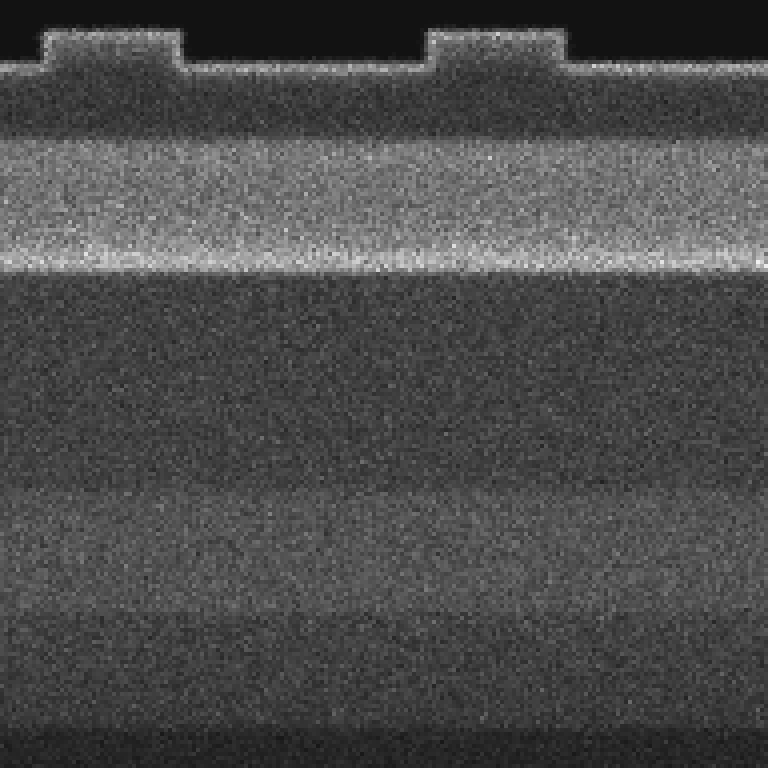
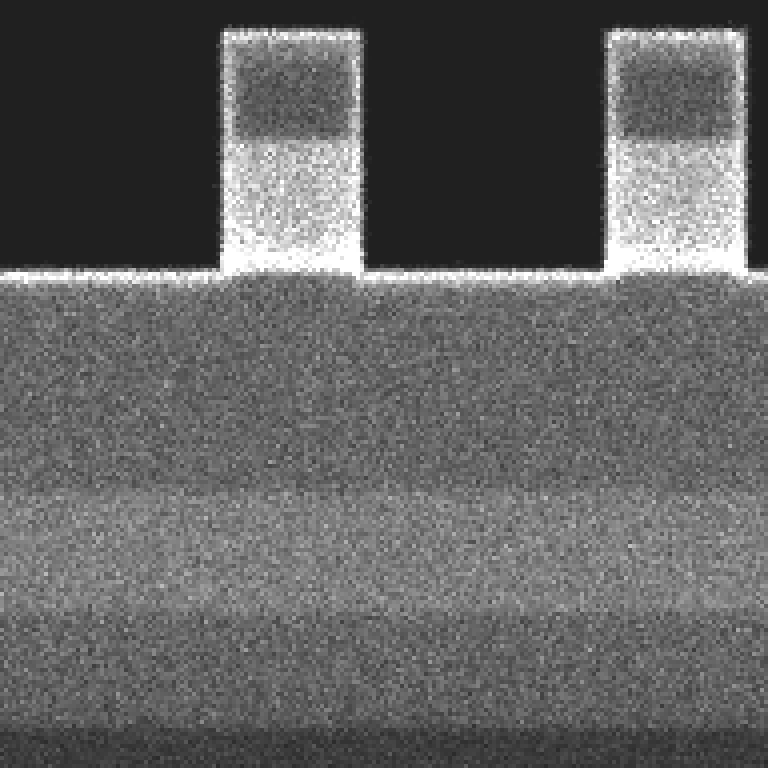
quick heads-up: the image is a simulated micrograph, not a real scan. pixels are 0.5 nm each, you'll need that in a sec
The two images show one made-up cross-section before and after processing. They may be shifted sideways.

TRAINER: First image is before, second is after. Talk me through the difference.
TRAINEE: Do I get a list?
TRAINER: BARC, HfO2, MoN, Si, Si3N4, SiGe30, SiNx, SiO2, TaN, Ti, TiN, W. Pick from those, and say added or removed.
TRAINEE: removed: HfO2 and SiNx and W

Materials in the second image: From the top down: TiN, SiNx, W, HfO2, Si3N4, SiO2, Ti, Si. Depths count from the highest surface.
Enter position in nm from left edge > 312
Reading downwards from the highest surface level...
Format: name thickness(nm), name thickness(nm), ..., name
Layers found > TiN 16, SiNx 38, W 56, HfO2 10, Si3N4 110, SiO2 60, Ti 58, Si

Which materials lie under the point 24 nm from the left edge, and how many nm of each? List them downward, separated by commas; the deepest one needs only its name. empty 120, Si3N4 110, SiO2 60, Ti 58, Si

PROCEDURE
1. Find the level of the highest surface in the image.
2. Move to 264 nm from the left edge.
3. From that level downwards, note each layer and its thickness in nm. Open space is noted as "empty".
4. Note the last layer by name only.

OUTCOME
empty 120, Si3N4 110, SiO2 60, Ti 58, Si